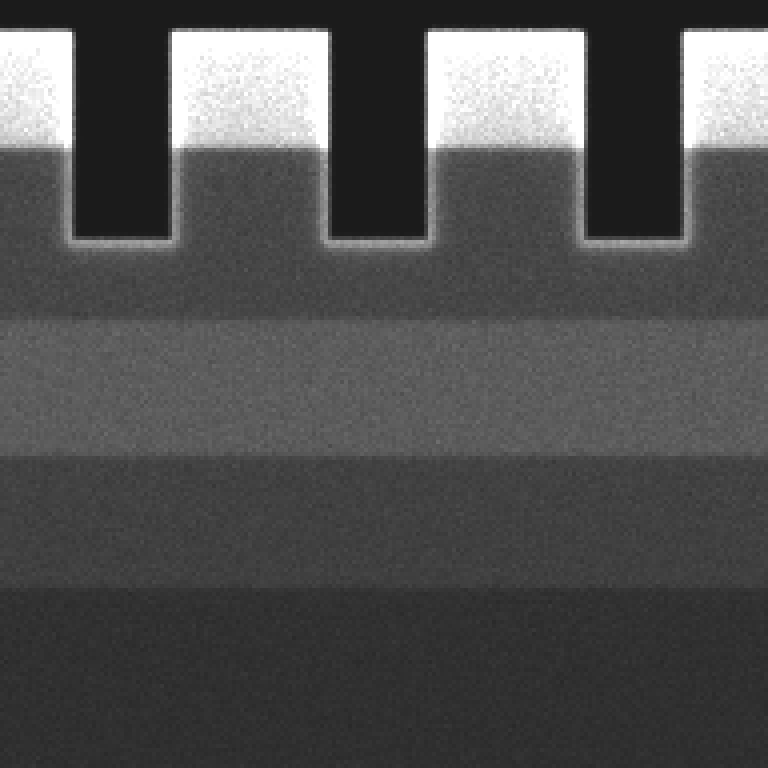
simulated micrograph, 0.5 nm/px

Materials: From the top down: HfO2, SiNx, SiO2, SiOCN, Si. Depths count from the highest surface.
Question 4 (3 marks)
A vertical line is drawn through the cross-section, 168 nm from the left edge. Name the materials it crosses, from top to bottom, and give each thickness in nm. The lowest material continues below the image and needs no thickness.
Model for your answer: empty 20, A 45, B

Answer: empty 104, SiNx 40, SiO2 68, SiOCN 66, Si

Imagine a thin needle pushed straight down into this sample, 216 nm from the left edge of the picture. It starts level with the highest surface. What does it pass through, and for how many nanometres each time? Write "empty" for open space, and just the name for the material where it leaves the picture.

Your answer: HfO2 58, SiNx 86, SiO2 68, SiOCN 66, Si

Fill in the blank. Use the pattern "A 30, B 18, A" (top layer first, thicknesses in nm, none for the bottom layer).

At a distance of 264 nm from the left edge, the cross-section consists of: HfO2 58, SiNx 86, SiO2 68, SiOCN 66, Si